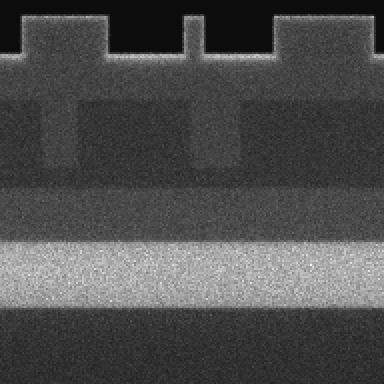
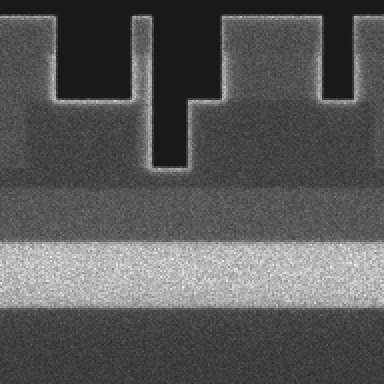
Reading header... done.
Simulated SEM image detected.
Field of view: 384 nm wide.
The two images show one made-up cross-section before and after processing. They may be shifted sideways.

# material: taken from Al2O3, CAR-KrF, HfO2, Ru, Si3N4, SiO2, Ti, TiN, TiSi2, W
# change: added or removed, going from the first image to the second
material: SiO2
change: removed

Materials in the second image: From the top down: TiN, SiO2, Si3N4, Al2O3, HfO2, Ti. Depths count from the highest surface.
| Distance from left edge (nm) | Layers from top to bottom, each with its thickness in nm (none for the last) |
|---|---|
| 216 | empty 84, Si3N4 88, Al2O3 54, HfO2 66, Ti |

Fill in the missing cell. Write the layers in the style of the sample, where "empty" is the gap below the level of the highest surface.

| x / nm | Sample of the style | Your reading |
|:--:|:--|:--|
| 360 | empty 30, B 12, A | TiN 38, SiO2 46, Si3N4 88, Al2O3 54, HfO2 66, Ti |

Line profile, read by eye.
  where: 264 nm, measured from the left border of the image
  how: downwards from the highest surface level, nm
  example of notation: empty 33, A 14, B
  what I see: TiN 38, SiO2 46, Si3N4 88, Al2O3 54, HfO2 66, Ti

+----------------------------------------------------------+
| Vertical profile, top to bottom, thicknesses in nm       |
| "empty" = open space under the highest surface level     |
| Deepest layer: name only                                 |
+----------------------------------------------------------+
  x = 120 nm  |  empty 84, Si3N4 88, Al2O3 54, HfO2 66, Ti